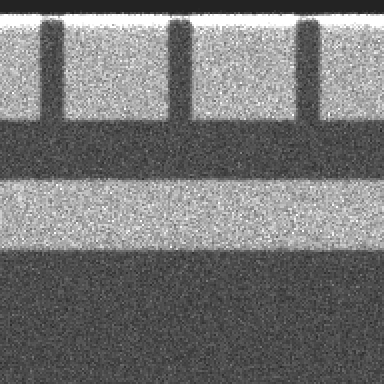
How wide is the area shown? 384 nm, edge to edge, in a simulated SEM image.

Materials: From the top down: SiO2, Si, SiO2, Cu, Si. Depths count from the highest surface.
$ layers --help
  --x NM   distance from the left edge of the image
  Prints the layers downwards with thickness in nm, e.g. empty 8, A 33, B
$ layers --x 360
SiO2 104, Si 60, SiO2 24, Cu 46, Si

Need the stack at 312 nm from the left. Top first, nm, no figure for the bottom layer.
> Si 164, SiO2 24, Cu 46, Si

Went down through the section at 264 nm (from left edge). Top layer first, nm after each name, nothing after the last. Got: SiO2 104, Si 60, SiO2 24, Cu 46, Si